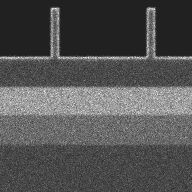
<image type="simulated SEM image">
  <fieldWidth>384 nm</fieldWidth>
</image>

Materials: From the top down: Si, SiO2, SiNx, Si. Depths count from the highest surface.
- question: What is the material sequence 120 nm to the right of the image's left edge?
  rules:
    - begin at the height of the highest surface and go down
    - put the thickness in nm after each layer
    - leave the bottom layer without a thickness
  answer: empty 98, Si 60, SiO2 56, SiNx 60, Si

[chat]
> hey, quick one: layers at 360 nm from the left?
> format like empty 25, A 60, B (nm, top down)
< empty 98, Si 60, SiO2 56, SiNx 60, Si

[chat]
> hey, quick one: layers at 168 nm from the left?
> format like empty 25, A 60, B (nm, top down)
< empty 98, Si 60, SiO2 56, SiNx 60, Si